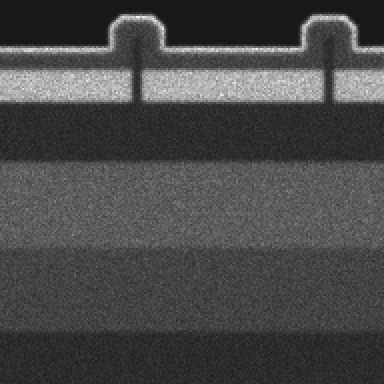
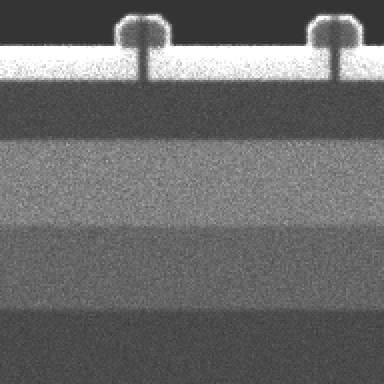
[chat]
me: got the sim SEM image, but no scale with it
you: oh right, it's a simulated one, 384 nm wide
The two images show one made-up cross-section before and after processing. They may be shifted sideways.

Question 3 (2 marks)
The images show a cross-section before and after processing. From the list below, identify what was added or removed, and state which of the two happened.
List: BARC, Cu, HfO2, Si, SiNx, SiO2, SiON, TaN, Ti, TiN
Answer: SiNx was removed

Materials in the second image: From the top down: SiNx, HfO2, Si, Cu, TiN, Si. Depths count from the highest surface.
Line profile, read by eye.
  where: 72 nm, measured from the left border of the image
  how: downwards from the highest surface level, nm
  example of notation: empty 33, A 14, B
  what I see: empty 32, HfO2 32, Si 60, Cu 86, TiN 84, Si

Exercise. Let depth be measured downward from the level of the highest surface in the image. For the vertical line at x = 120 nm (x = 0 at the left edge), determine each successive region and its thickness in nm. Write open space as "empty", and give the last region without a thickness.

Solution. empty 6, SiNx 26, HfO2 32, Si 60, Cu 86, TiN 84, Si